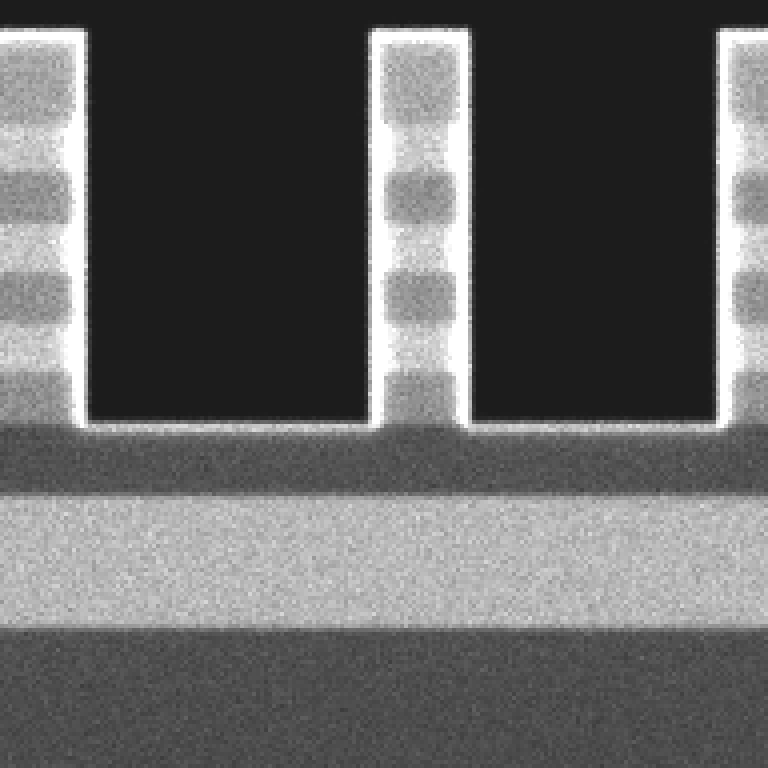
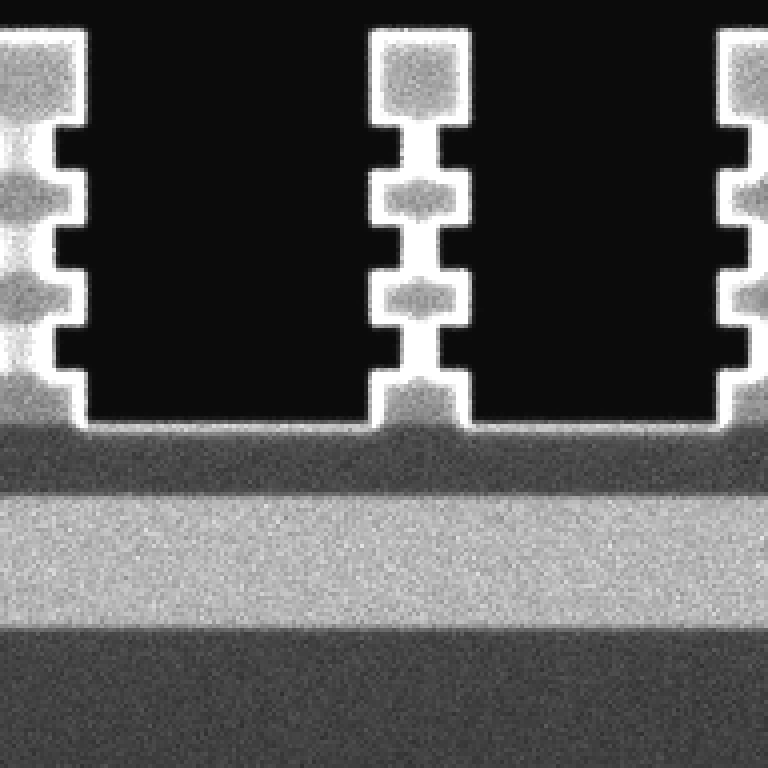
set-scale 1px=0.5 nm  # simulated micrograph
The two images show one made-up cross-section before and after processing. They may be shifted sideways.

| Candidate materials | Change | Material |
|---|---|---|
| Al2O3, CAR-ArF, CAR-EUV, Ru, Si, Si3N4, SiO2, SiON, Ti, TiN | removed | Al2O3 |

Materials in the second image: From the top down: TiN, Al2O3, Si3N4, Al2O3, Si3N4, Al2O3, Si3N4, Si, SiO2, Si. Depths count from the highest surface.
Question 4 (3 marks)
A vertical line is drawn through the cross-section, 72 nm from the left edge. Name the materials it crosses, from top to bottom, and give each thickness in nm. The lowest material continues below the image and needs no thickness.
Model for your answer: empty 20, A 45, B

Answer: empty 196, Si 36, SiO2 66, Si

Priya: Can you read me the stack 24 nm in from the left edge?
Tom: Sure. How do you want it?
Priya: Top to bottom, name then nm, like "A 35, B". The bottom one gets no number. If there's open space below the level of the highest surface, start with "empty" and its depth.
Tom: TiN 46, Al2O3 24, Si3N4 26, Al2O3 24, Si3N4 26, Al2O3 24, Si3N4 26, Si 36, SiO2 66, Si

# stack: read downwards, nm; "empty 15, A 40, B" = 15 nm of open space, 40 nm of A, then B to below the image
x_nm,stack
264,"empty 196, Si 36, SiO2 66, Si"